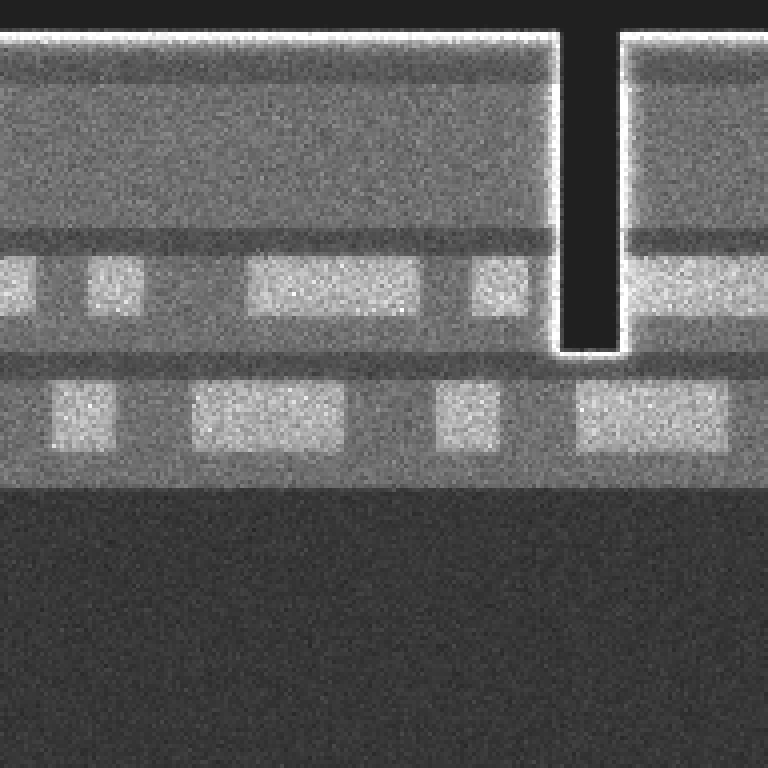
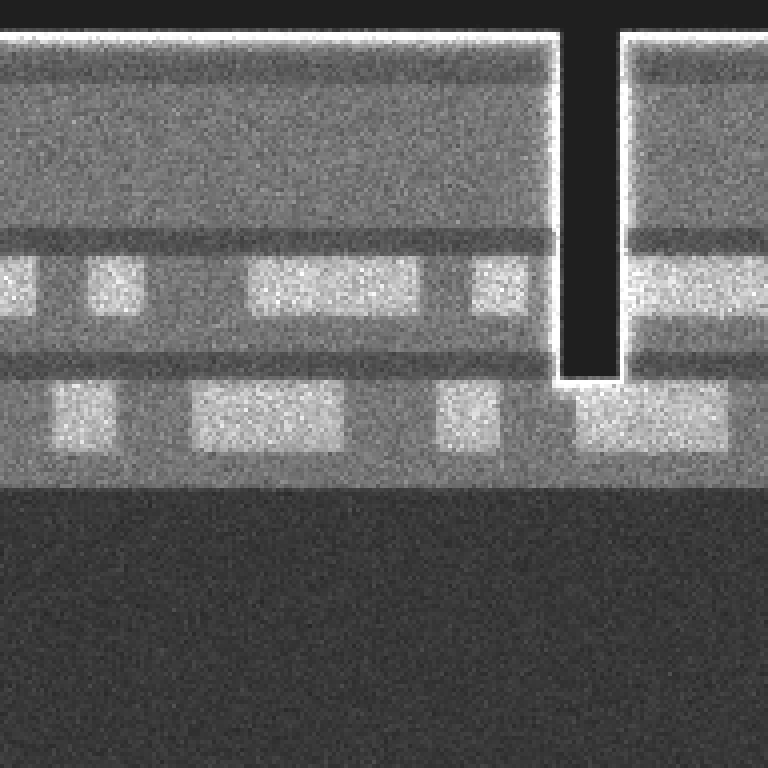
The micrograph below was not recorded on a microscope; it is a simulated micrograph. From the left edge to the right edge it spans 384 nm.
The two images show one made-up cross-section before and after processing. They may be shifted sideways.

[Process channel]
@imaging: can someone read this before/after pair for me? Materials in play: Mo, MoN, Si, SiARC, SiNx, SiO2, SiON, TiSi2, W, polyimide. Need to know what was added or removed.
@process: SiNx removed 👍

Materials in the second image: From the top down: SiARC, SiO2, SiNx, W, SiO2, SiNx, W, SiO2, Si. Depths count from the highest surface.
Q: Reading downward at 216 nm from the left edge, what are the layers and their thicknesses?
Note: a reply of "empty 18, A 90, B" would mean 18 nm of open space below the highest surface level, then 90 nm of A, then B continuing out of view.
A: SiARC 26, SiO2 72, SiNx 14, SiO2 48, SiNx 14, SiO2 54, Si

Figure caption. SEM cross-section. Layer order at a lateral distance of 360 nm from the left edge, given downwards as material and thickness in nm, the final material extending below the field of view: SiARC 26, SiO2 72, SiNx 14, W 30, SiO2 18, SiNx 14, W 36, SiO2 18, Si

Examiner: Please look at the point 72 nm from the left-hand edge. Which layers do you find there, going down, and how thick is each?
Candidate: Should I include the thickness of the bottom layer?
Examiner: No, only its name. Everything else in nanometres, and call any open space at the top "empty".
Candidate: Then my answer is SiARC 26, SiO2 72, SiNx 14, SiO2 48, SiNx 14, SiO2 54, Si